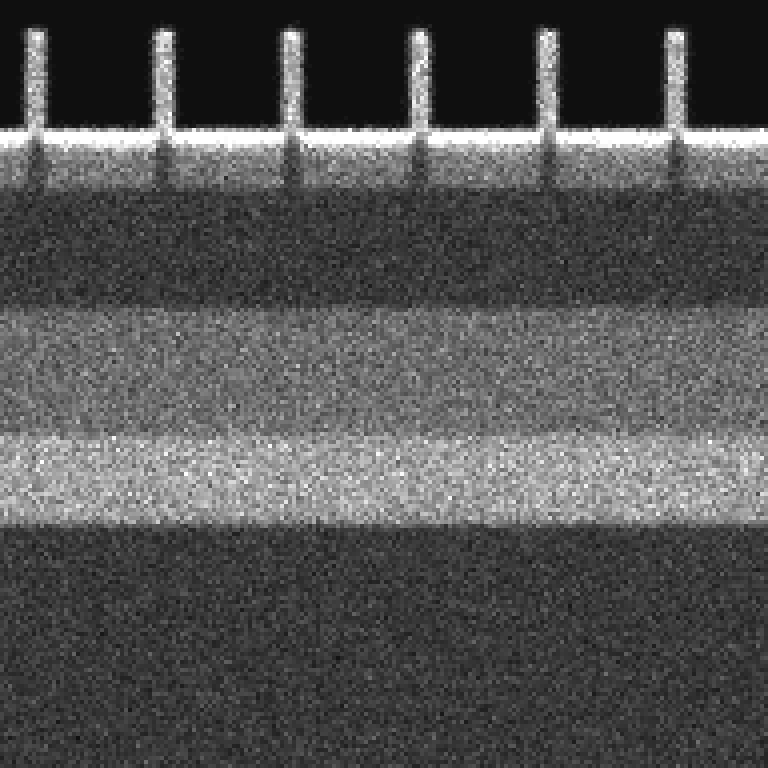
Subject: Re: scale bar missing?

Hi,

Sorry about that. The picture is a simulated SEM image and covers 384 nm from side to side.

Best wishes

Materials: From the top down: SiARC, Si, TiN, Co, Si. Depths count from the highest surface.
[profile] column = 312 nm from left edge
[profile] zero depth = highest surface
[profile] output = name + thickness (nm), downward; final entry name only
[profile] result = empty 50, SiARC 28, Si 60, TiN 64, Co 44, Si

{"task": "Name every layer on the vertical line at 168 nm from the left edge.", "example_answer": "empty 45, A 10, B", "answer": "empty 50, SiARC 28, Si 60, TiN 64, Co 44, Si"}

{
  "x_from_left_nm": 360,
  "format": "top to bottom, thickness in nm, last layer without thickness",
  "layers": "empty 50, SiARC 28, Si 60, TiN 64, Co 44, Si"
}